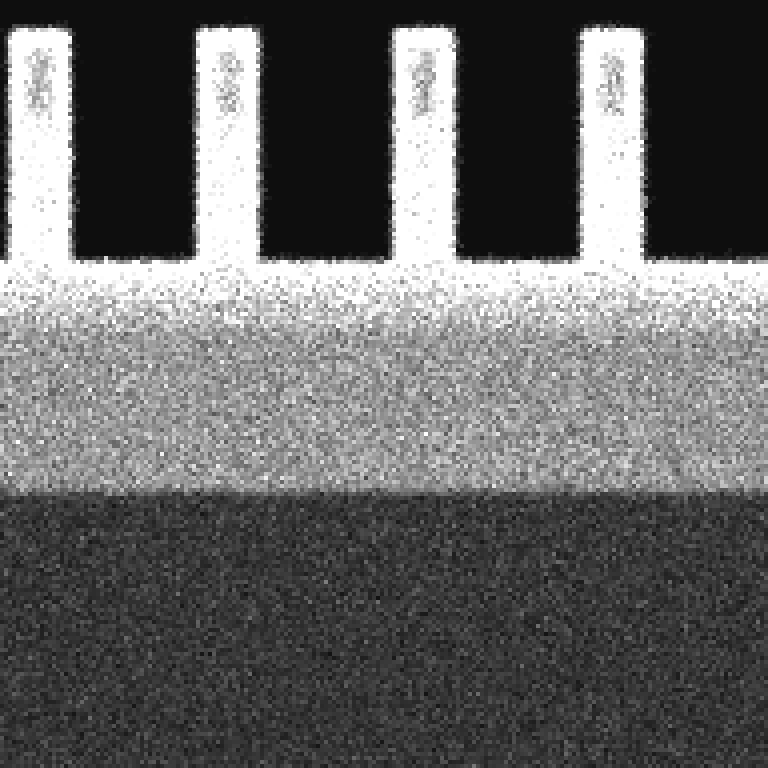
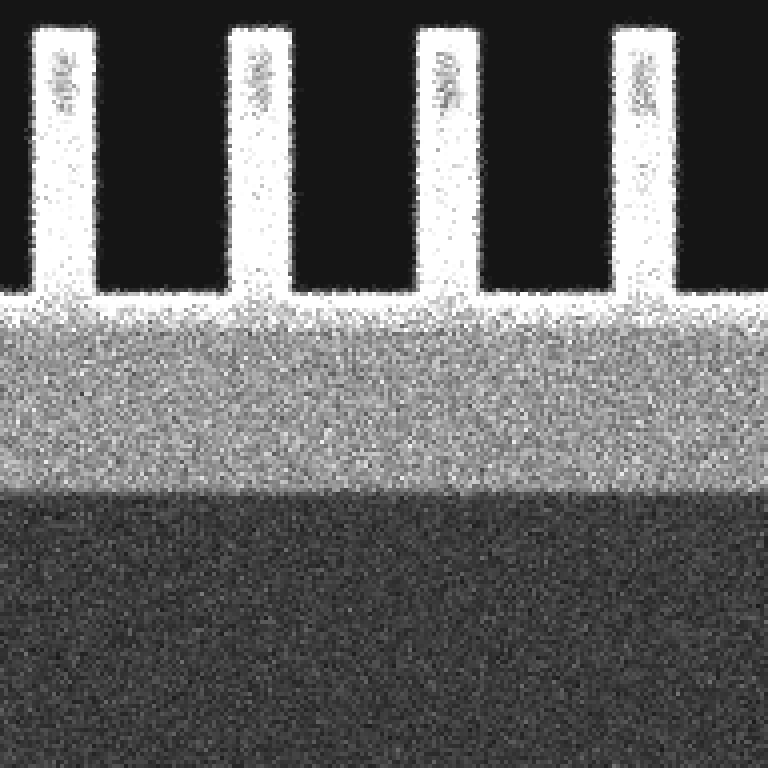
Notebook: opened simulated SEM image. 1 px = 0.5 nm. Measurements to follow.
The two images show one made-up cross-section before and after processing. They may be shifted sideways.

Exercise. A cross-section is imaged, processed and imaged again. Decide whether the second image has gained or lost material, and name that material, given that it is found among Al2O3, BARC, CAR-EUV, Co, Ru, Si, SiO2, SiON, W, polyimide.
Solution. removed: Ru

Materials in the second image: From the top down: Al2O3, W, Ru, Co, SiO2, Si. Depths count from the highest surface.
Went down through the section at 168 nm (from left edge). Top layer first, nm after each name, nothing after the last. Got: empty 132, Co 16, SiO2 82, Si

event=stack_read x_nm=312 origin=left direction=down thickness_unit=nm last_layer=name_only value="Al2O3 42, W 74, Ru 16, Co 16, SiO2 82, Si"